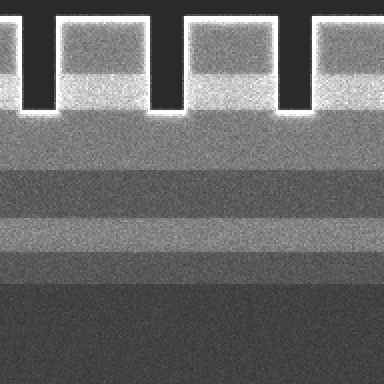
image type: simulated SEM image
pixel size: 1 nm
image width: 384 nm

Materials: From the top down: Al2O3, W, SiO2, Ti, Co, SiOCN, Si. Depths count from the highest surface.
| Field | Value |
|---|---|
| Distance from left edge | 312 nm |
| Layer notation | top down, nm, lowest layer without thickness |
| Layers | Al2O3 58, W 36, SiO2 60, Ti 48, Co 34, SiOCN 32, Si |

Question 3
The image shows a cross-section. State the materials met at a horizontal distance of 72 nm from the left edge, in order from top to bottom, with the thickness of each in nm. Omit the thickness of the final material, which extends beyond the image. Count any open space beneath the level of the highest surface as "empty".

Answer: Al2O3 58, W 36, SiO2 60, Ti 48, Co 34, SiOCN 32, Si